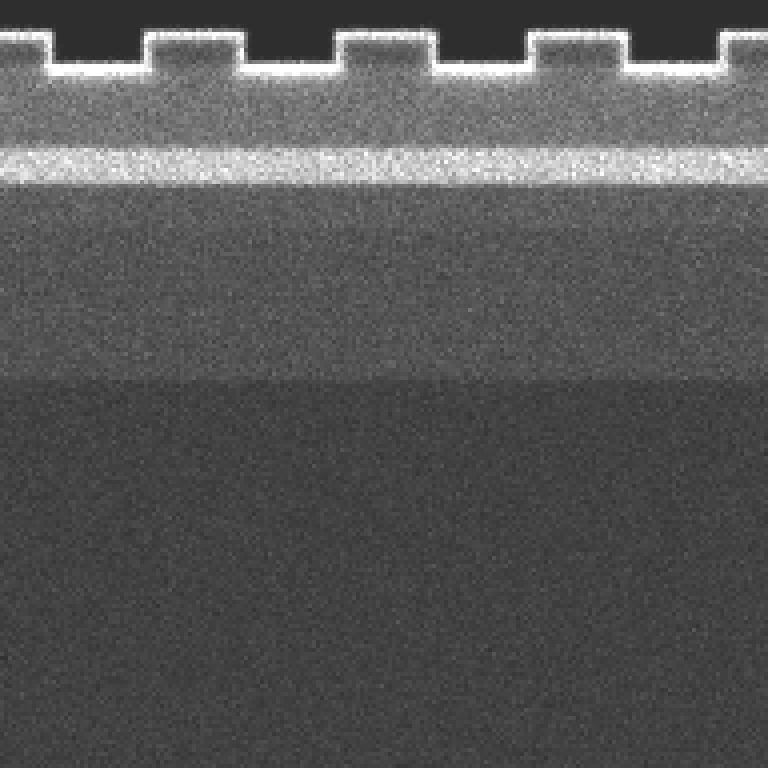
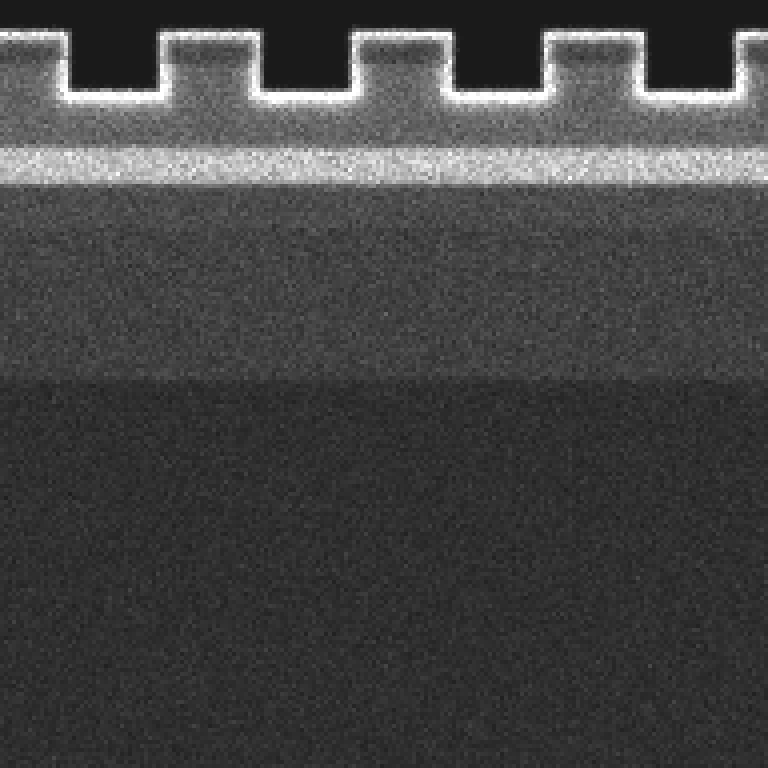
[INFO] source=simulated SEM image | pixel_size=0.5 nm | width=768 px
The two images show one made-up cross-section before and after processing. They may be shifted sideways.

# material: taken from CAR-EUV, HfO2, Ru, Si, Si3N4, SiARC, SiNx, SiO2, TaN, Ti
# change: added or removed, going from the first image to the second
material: SiO2
change: removed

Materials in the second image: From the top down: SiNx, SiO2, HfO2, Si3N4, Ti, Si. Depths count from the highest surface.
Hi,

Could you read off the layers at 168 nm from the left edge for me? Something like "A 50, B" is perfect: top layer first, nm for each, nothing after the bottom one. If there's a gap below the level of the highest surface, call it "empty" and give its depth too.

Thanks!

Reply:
empty 30, SiO2 28, HfO2 18, Si3N4 22, Ti 76, Si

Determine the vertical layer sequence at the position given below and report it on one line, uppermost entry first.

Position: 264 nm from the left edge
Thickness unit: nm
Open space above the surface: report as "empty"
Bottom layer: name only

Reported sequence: empty 30, SiO2 28, HfO2 18, Si3N4 22, Ti 76, Si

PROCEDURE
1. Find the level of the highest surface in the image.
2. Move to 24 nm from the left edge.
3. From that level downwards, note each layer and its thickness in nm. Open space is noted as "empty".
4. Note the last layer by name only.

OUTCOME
SiNx 16, SiO2 42, HfO2 18, Si3N4 22, Ti 76, Si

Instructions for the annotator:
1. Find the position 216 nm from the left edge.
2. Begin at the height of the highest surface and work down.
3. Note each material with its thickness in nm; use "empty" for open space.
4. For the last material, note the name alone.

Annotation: SiNx 16, SiO2 42, HfO2 18, Si3N4 22, Ti 76, Si